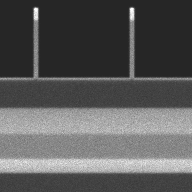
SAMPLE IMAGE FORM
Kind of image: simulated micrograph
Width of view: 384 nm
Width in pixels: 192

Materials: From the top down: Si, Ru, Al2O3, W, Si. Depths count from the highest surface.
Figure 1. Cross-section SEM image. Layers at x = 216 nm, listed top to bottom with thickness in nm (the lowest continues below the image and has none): empty 140, Si 60, Ru 52, Al2O3 50, W 28, Si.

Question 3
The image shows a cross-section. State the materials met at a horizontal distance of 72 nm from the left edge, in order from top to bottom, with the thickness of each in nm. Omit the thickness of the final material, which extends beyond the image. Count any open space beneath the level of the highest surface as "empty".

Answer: Si 200, Ru 52, Al2O3 50, W 28, Si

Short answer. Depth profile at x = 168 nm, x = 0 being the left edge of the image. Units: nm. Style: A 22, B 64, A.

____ empty 140, Si 60, Ru 52, Al2O3 50, W 28, Si